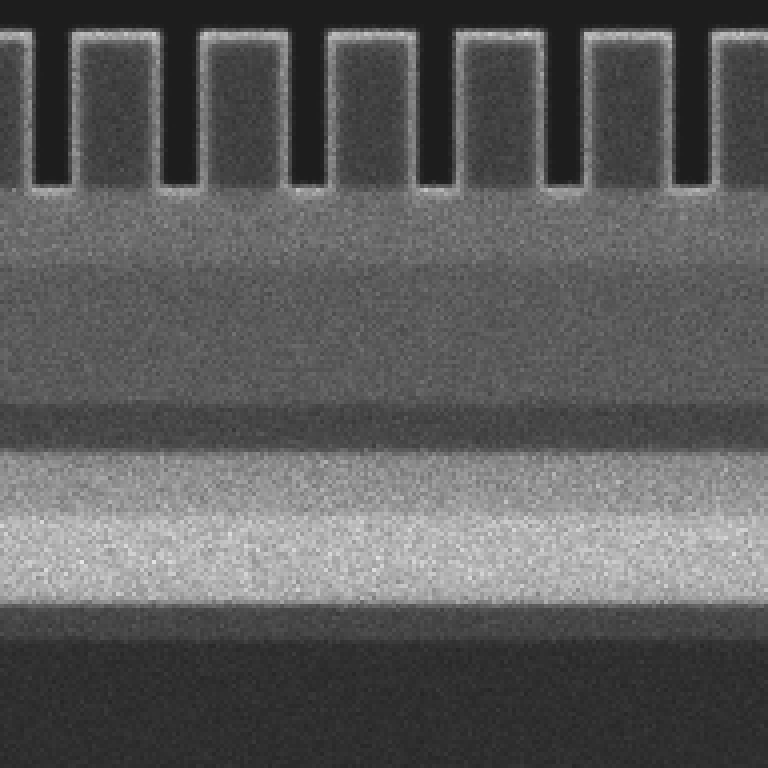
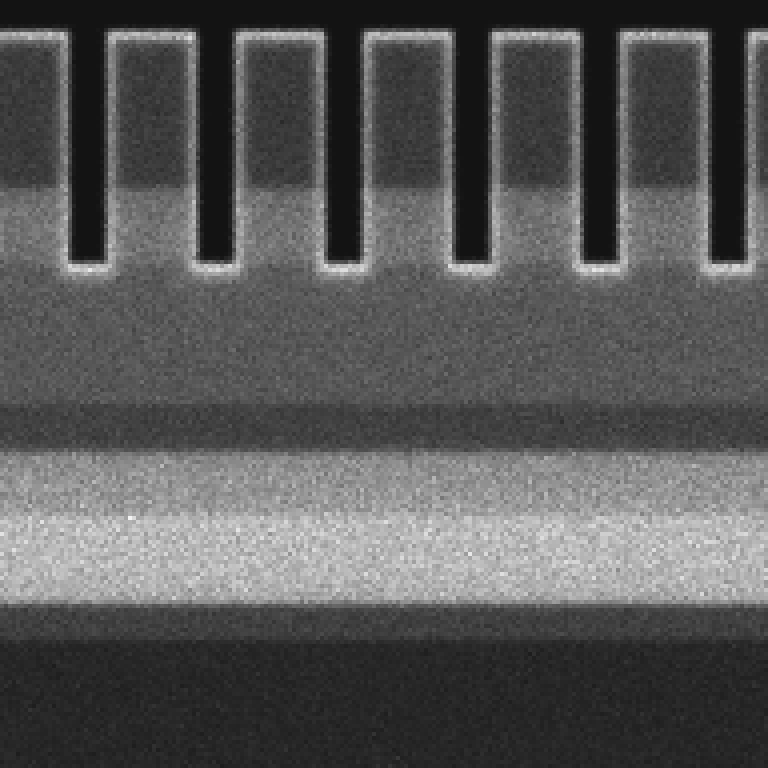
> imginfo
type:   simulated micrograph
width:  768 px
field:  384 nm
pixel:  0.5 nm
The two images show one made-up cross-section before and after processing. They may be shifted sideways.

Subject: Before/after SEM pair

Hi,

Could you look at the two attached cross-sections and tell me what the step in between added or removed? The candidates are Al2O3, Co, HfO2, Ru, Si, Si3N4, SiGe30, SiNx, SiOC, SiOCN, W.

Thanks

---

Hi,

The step removed Co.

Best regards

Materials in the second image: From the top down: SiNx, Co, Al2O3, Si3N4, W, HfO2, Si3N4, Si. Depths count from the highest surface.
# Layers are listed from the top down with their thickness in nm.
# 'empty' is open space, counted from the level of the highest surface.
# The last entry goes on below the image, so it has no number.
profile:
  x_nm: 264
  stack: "SiNx 78, Co 38, Al2O3 70, Si3N4 24, W 32, HfO2 44, Si3N4 18, Si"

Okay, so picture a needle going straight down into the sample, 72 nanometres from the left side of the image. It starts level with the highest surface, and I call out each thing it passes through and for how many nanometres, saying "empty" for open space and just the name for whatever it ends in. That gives SiNx 78, Co 38, Al2O3 70, Si3N4 24, W 32, HfO2 44, Si3N4 18, Si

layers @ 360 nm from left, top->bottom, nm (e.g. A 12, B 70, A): empty 116, Al2O3 70, Si3N4 24, W 32, HfO2 44, Si3N4 18, Si